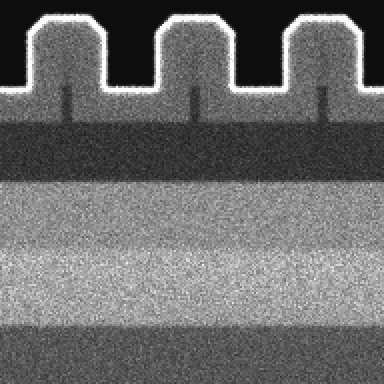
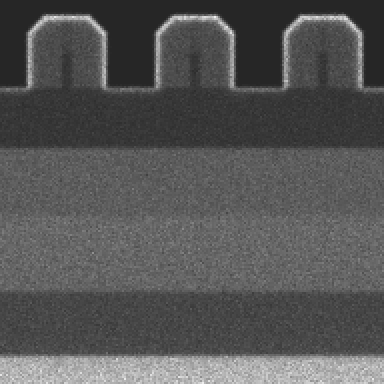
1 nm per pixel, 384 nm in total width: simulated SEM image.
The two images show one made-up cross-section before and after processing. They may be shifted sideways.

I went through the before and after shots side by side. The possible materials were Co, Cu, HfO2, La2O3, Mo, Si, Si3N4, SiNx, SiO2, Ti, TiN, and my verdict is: removed, Si3N4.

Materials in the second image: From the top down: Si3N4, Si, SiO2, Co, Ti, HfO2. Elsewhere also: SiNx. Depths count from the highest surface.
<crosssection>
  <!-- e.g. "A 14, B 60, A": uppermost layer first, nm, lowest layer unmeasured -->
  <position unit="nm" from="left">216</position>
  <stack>Si3N4 72, Si 60, SiO2 68, Co 76, Ti 64, HfO2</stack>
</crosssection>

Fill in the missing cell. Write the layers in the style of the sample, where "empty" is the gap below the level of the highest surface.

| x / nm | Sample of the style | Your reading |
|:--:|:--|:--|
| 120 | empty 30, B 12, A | empty 72, Si 60, SiO2 68, Co 76, Ti 64, HfO2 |